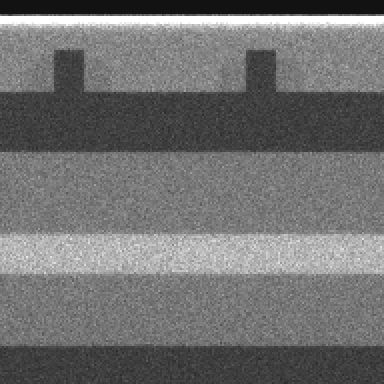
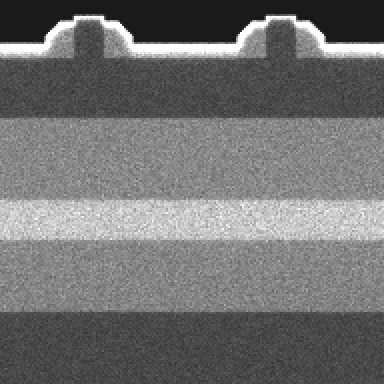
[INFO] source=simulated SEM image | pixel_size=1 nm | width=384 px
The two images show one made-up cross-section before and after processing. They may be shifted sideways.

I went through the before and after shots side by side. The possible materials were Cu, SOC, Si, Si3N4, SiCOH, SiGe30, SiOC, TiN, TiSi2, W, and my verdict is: removed, SOC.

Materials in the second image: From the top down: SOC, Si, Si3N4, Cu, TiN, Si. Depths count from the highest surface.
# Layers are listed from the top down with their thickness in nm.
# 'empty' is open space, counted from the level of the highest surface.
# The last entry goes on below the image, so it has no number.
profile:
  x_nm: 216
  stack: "empty 28, SOC 14, Si 60, Si3N4 82, Cu 40, TiN 72, Si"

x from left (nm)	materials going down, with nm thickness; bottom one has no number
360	empty 28, SOC 14, Si 60, Si3N4 82, Cu 40, TiN 72, Si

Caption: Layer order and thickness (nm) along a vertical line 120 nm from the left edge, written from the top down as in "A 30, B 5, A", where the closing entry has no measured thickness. empty 10, Si3N4 32, Si 60, Si3N4 82, Cu 40, TiN 72, Si